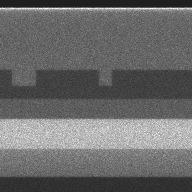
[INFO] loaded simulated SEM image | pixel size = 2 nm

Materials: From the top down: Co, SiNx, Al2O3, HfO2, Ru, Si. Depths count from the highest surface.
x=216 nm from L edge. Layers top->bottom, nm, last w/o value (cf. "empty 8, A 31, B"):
Co 156, SiNx 26, Al2O3 40, HfO2 60, Ru 56, Si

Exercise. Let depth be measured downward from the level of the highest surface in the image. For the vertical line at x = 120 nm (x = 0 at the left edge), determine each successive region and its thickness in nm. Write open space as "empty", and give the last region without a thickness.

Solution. Co 124, SiNx 58, Al2O3 40, HfO2 60, Ru 56, Si